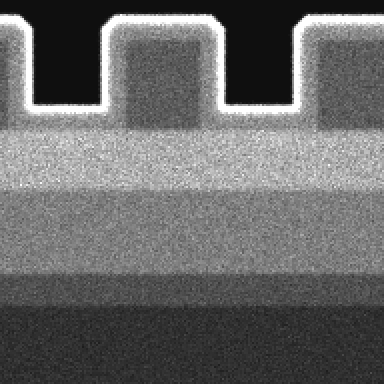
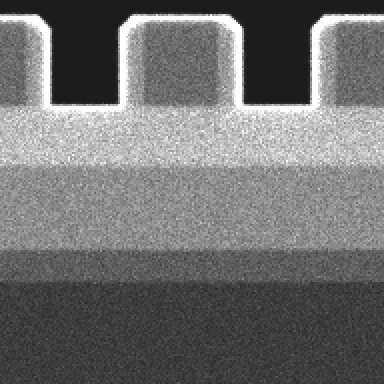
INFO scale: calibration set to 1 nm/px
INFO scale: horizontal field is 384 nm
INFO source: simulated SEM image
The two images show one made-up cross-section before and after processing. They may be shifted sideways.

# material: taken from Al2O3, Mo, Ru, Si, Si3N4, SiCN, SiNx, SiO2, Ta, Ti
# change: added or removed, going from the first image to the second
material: Al2O3
change: removed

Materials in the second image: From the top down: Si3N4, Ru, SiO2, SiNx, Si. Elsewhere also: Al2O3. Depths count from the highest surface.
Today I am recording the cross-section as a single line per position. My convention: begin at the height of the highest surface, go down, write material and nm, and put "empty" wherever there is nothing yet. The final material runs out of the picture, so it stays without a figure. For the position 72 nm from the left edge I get empty 90, Ru 60, SiO2 84, SiNx 32, Si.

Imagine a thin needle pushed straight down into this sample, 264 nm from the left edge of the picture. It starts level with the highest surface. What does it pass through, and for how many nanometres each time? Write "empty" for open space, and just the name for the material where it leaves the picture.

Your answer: empty 90, Ru 60, SiO2 84, SiNx 32, Si